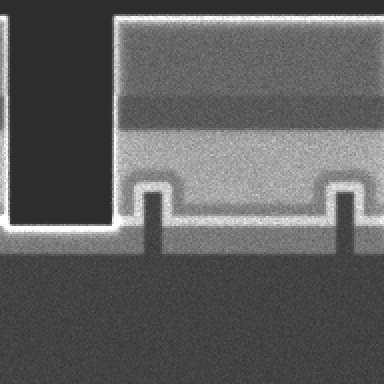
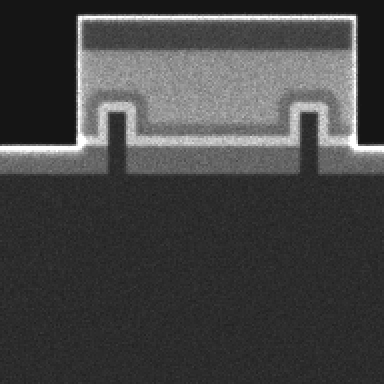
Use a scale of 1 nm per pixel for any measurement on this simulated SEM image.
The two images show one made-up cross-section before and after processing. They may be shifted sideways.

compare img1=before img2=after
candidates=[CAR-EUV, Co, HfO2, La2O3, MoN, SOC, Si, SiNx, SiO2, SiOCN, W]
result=removed:SOC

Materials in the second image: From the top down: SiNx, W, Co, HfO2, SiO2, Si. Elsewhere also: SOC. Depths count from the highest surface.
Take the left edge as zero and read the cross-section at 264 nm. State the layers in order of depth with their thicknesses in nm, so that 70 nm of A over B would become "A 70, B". SiNx 34, W 74, Co 12, HfO2 10, SiO2 28, Si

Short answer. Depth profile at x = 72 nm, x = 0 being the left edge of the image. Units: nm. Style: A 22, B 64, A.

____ empty 130, SiO2 28, Si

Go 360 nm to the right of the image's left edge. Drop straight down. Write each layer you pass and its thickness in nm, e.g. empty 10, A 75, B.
empty 130, SiO2 28, Si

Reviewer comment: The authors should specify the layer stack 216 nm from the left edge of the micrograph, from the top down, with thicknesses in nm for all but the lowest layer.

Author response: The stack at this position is SiNx 34, W 74, Co 12, HfO2 10, SiO2 28, Si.